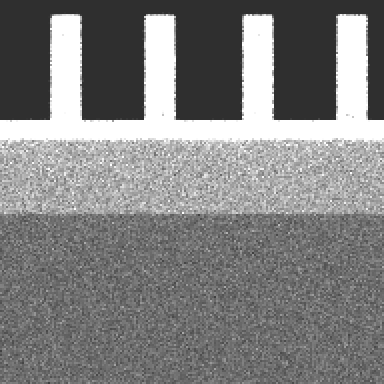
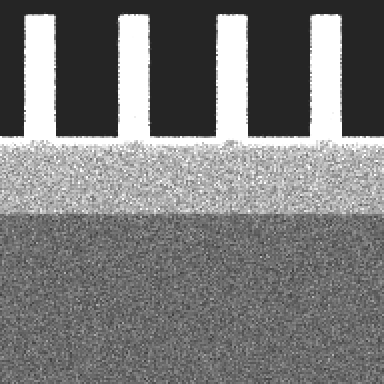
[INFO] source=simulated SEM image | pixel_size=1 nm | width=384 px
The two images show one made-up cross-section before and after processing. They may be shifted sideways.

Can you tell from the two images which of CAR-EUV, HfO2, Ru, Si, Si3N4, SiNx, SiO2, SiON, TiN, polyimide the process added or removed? Yes, it removed HfO2.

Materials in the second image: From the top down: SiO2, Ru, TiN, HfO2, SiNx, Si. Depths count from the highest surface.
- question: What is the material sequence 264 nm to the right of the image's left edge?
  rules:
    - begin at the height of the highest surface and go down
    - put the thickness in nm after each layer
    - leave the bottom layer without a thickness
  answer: empty 122, SiNx 76, Si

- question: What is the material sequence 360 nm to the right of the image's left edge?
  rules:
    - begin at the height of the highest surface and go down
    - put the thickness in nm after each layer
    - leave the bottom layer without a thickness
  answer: empty 122, SiNx 76, Si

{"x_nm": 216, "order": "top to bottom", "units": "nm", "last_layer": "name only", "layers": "empty 122, SiNx 76, Si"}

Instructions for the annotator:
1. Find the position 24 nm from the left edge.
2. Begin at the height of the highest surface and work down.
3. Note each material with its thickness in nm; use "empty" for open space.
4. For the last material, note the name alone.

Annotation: empty 122, SiNx 76, Si